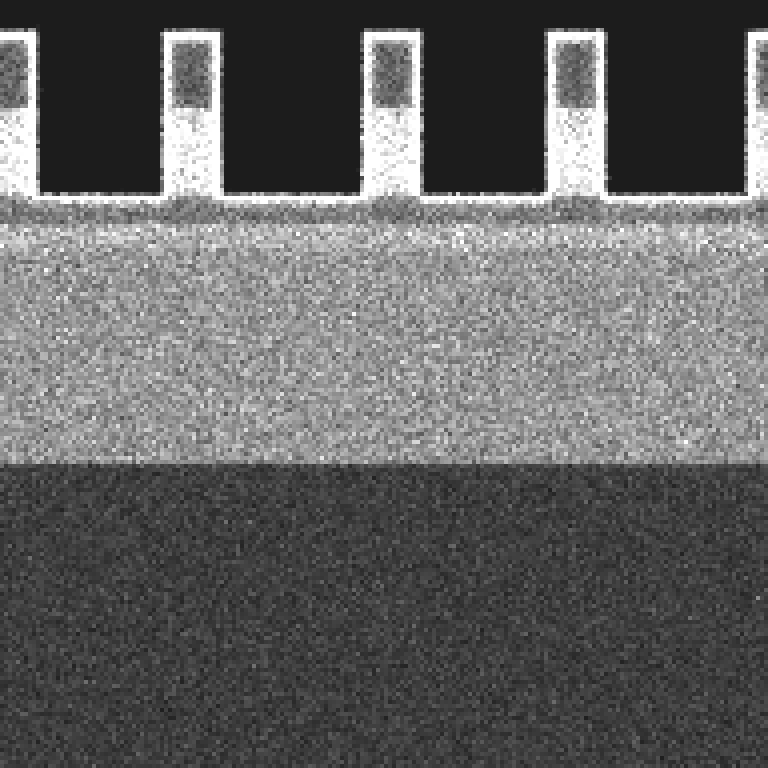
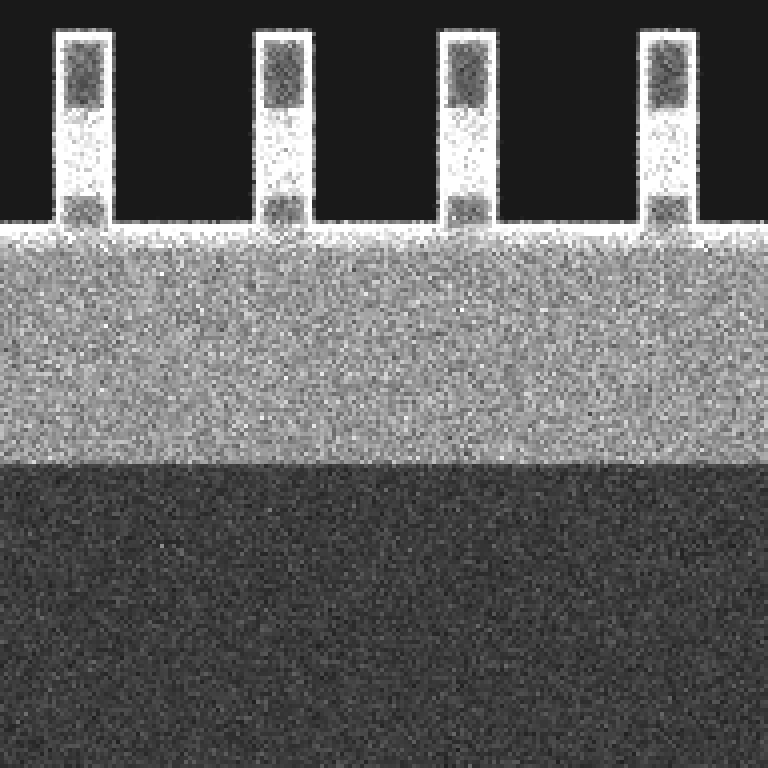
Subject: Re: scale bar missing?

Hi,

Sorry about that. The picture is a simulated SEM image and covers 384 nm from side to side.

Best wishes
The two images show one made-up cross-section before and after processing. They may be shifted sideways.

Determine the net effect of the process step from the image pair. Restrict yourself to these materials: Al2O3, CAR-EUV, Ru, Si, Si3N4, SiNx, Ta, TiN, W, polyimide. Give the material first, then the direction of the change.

TiN: removed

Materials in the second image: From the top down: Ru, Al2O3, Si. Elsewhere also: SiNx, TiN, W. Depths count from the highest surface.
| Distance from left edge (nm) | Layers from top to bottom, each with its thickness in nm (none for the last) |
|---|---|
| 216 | empty 96, Ru 12, Al2O3 108, Si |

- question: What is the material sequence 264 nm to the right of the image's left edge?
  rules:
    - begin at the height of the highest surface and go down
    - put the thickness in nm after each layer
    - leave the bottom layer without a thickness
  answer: empty 96, Ru 12, Al2O3 108, Si